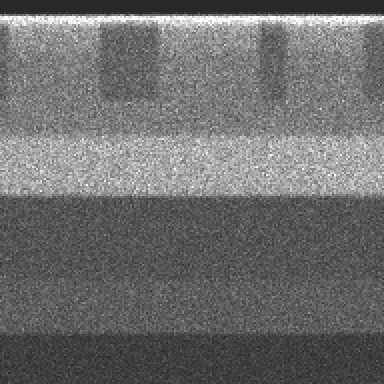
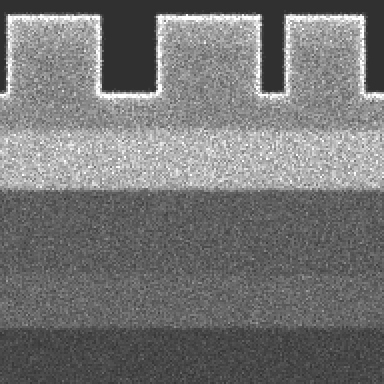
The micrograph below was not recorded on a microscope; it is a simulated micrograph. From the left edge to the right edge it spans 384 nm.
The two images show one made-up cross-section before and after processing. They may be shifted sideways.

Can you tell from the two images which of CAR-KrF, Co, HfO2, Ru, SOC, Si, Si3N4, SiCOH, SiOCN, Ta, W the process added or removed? Yes, it removed SOC.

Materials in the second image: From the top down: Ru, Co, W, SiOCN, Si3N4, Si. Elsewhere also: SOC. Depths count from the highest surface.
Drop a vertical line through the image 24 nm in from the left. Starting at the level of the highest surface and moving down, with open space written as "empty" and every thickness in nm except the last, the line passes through Ru 30, Co 84, W 60, SiOCN 84, Si3N4 54, Si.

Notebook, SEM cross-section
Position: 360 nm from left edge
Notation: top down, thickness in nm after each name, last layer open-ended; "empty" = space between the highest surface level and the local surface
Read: Ru 30, Co 84, W 60, SiOCN 84, Si3N4 54, Si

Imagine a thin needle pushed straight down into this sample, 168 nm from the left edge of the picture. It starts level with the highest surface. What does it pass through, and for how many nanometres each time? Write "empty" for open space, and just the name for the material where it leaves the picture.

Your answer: Ru 30, Co 84, W 60, SiOCN 84, Si3N4 54, Si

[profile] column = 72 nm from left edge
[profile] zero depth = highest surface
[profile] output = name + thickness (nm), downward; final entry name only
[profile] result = Ru 30, Co 84, W 60, SiOCN 84, Si3N4 54, Si